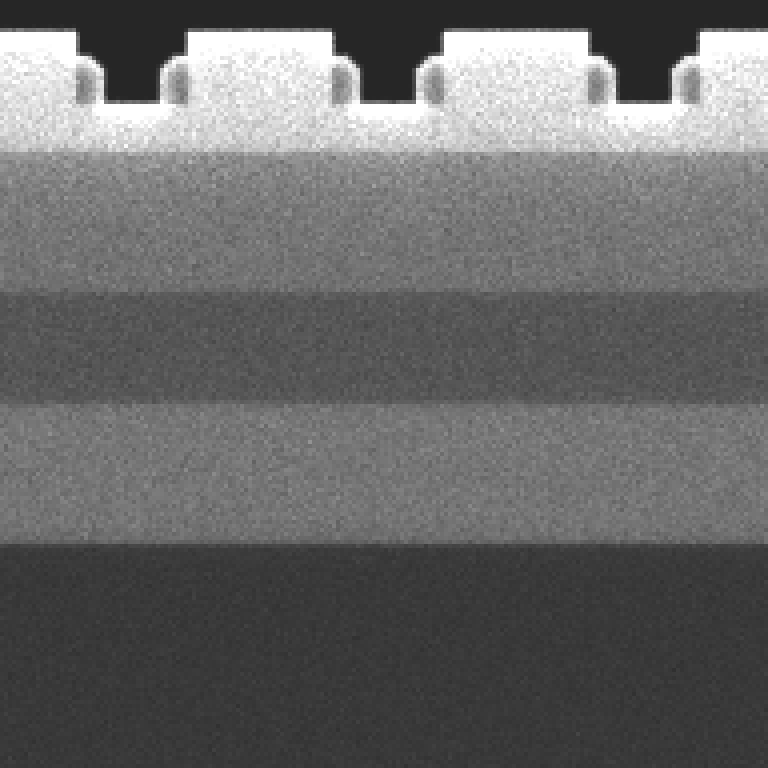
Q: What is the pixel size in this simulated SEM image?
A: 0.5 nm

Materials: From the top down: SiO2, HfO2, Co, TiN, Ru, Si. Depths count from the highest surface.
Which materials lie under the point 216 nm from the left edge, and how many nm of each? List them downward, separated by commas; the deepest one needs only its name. empty 12, SiO2 24, HfO2 24, Co 70, TiN 56, Ru 70, Si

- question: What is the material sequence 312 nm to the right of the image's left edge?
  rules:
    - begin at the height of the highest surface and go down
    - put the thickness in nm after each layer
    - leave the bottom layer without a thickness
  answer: empty 36, HfO2 24, Co 70, TiN 56, Ru 70, Si